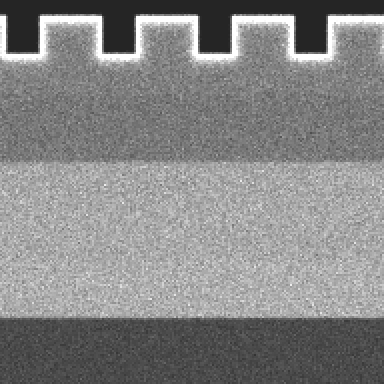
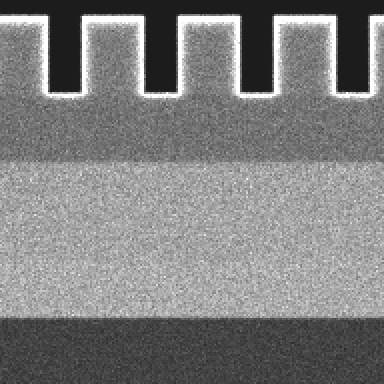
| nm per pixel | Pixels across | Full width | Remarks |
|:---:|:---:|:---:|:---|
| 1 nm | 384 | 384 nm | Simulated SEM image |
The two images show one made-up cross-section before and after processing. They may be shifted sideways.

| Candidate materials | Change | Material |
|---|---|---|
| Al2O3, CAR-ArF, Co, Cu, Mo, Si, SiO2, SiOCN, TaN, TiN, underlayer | removed | underlayer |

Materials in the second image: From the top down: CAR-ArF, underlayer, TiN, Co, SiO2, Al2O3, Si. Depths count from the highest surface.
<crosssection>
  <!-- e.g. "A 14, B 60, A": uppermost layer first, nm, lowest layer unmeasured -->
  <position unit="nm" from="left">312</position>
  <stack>CAR-ArF 38, underlayer 40, TiN 68, Co 34, SiO2 64, Al2O3 58, Si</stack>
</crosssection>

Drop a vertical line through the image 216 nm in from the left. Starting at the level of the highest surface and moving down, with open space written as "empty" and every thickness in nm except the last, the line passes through CAR-ArF 38, underlayer 40, TiN 68, Co 34, SiO2 64, Al2O3 58, Si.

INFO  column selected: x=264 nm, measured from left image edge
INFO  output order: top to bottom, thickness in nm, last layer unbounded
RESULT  empty 78, TiN 68, Co 34, SiO2 64, Al2O3 58, Si